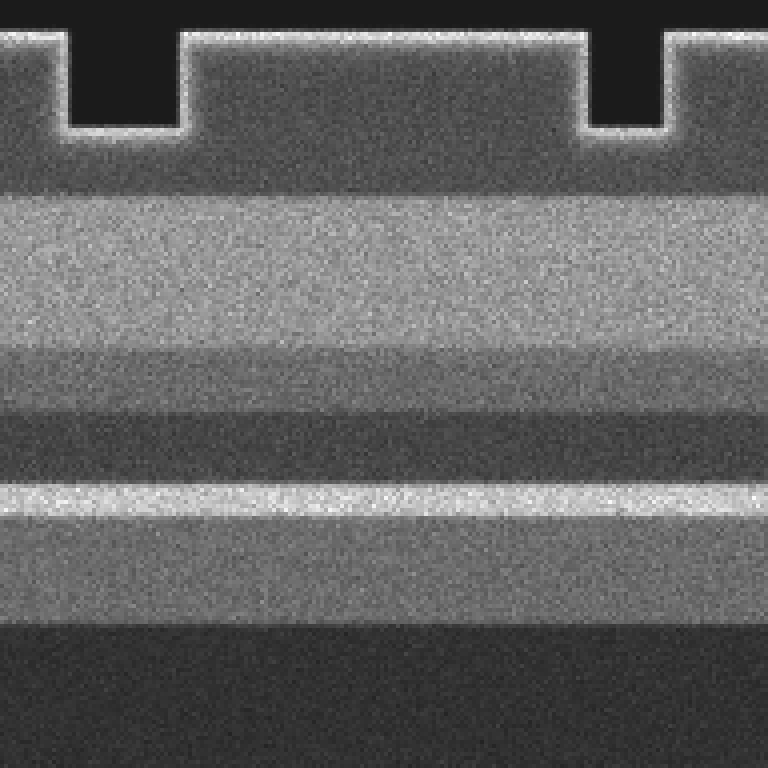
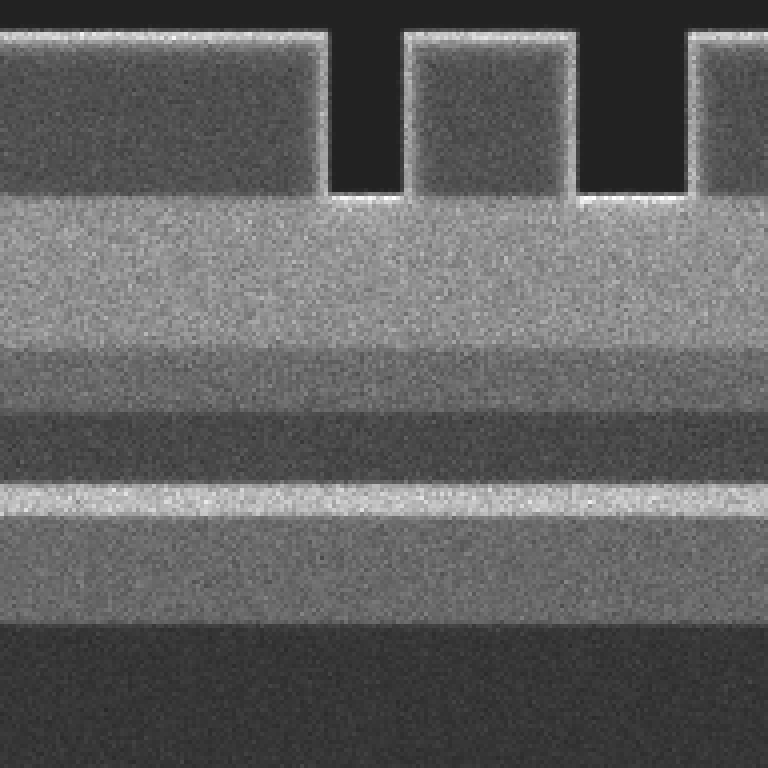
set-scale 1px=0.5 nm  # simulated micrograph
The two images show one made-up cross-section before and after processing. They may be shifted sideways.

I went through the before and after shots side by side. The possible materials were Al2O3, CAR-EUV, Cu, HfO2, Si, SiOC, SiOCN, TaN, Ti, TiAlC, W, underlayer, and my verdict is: removed, underlayer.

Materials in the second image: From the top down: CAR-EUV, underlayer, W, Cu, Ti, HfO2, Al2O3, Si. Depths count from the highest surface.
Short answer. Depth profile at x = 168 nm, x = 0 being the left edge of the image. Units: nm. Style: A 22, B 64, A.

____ empty 82, W 76, Cu 32, Ti 36, HfO2 16, Al2O3 54, Si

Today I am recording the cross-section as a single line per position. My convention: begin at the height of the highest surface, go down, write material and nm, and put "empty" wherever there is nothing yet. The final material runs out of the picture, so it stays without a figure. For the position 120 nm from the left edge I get CAR-EUV 48, underlayer 34, W 76, Cu 32, Ti 36, HfO2 16, Al2O3 54, Si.